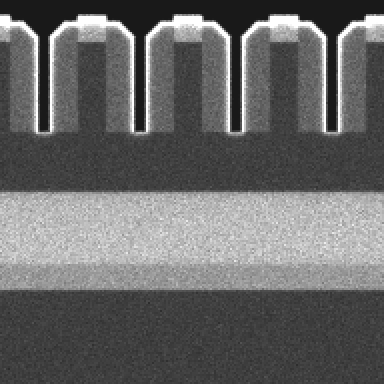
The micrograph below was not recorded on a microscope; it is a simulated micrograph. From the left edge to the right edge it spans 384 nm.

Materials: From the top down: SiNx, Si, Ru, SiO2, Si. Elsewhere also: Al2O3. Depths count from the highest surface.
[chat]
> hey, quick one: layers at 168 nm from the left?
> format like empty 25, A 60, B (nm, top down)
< empty 6, SiNx 110, Si 60, Ru 72, SiO2 26, Si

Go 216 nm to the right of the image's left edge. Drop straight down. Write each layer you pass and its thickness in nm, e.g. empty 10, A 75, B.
empty 8, SiNx 108, Si 60, Ru 72, SiO2 26, Si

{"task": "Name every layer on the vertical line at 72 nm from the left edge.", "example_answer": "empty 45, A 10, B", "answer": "empty 6, SiNx 110, Si 60, Ru 72, SiO2 26, Si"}